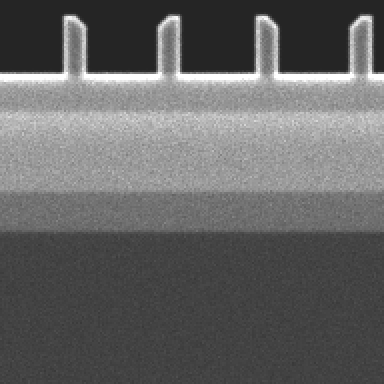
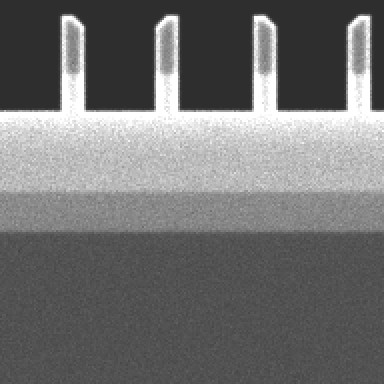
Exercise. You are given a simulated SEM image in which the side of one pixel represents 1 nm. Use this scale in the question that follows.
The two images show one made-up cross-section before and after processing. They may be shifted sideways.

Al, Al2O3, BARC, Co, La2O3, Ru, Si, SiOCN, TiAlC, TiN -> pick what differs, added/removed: Al2O3 removed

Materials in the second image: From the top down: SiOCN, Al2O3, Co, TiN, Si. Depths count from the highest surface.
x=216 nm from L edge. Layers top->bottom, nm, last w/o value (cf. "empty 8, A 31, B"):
empty 96, Co 80, TiN 40, Si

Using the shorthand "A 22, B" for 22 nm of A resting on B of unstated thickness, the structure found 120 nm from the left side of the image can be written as empty 96, Co 80, TiN 40, Si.